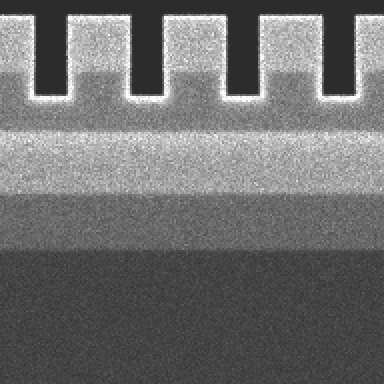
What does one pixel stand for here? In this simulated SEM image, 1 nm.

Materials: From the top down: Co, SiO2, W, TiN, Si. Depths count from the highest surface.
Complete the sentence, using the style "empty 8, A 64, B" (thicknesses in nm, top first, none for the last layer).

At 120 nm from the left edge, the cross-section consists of Co 56, SiO2 60, W 62, TiN 56, Si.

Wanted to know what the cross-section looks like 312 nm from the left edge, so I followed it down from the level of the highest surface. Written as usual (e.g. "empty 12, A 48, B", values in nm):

Co 56, SiO2 60, W 62, TiN 56, Si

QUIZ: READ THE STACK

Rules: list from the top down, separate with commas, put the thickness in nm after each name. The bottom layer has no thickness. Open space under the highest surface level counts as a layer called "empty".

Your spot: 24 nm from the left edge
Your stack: Co 56, SiO2 60, W 62, TiN 56, Si